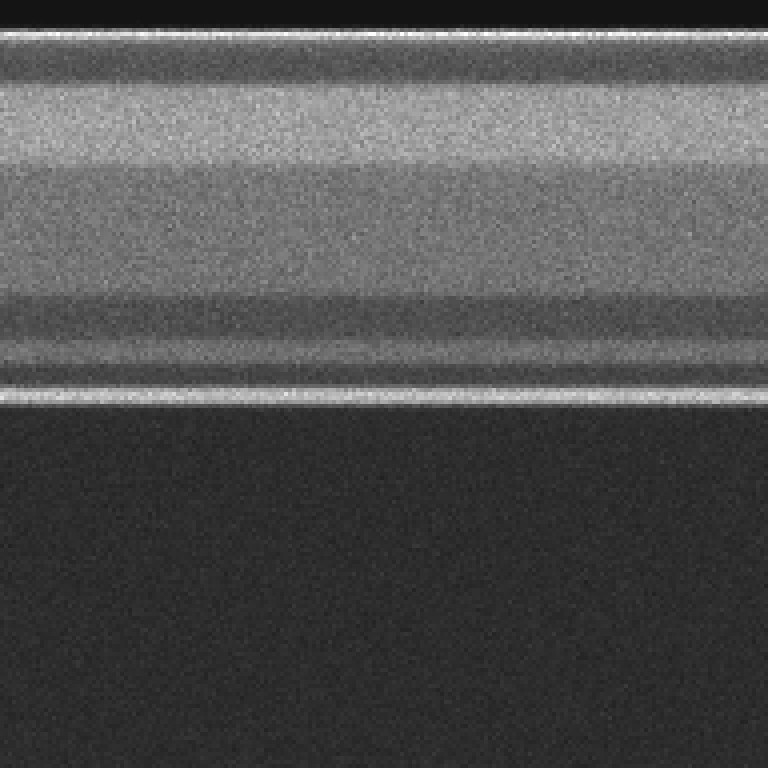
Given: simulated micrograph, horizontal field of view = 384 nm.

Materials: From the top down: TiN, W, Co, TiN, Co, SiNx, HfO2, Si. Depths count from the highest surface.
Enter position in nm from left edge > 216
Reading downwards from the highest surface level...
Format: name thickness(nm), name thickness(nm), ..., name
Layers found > TiN 26, W 40, Co 66, TiN 22, Co 12, SiNx 12, HfO2 8, Si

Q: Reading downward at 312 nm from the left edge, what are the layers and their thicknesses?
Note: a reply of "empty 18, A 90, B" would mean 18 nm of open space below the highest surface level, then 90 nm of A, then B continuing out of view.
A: TiN 26, W 40, Co 66, TiN 22, Co 12, SiNx 12, HfO2 8, Si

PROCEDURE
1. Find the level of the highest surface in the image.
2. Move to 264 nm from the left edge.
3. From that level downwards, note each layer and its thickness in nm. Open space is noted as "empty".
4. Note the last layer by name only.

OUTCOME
TiN 26, W 40, Co 66, TiN 22, Co 12, SiNx 12, HfO2 8, Si